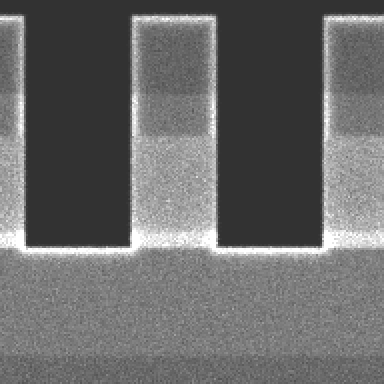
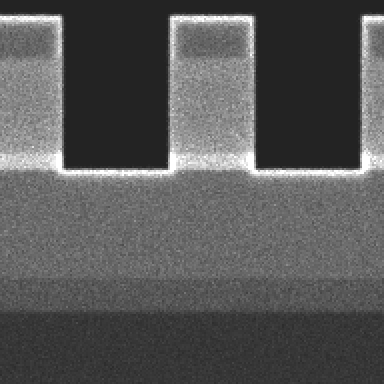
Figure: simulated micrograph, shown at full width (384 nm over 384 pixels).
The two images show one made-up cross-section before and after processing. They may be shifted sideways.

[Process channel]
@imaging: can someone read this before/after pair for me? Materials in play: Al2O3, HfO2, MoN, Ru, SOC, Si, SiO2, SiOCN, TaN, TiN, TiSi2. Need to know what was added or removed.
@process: SOC removed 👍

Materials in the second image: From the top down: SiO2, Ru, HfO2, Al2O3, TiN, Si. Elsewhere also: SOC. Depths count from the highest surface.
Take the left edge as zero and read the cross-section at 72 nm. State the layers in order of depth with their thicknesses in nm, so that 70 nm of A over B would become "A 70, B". empty 154, Al2O3 108, TiN 34, Si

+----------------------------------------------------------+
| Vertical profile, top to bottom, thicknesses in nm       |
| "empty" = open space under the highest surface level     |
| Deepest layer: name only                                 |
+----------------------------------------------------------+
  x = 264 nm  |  empty 154, Al2O3 108, TiN 34, Si